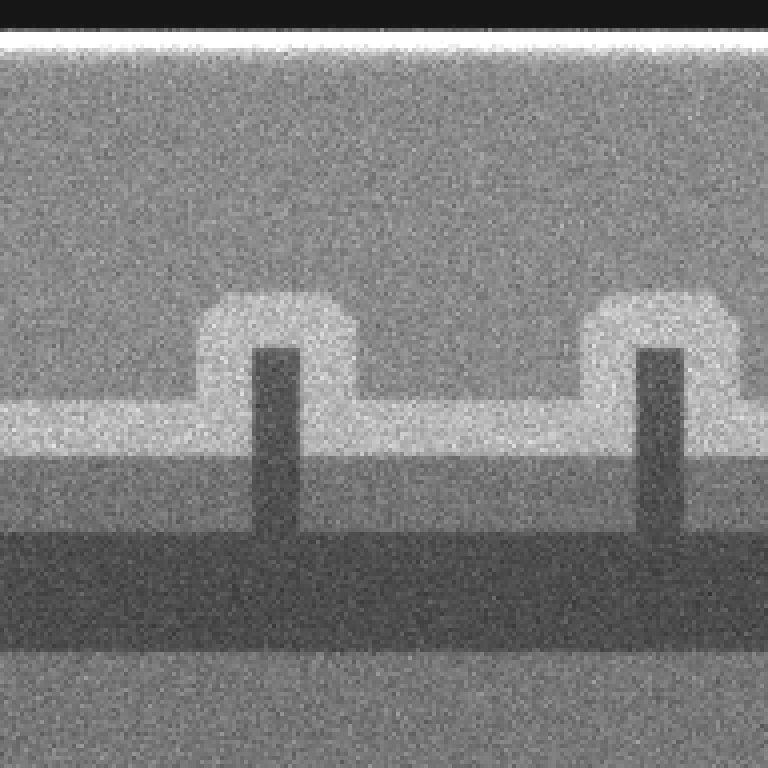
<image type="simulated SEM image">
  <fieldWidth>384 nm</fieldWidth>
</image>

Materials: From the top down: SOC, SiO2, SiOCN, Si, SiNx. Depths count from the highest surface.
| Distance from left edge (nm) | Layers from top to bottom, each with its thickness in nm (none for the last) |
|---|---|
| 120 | SOC 130, SiO2 82, SiOCN 38, Si 60, SiNx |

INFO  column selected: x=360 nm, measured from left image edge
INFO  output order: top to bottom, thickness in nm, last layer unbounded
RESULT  SOC 136, SiO2 76, SiOCN 38, Si 60, SiNx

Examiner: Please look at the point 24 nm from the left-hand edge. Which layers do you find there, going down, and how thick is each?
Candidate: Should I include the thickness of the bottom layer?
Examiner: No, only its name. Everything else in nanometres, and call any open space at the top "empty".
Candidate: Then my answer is SOC 184, SiO2 28, SiOCN 38, Si 60, SiNx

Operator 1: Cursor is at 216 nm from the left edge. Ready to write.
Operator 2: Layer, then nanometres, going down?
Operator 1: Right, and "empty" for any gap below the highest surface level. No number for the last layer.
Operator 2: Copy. SOC 184, SiO2 28, SiOCN 38, Si 60, SiNx